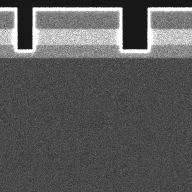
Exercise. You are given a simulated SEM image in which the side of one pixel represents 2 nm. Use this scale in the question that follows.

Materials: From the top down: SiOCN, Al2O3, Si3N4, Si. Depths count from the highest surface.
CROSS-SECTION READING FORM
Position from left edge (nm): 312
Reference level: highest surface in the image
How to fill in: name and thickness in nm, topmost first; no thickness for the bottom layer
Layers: SiOCN 42, Al2O3 32, Si3N4 26, Si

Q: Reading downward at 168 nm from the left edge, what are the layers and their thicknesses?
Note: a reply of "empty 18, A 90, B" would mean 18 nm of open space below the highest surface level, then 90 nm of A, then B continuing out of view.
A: SiOCN 42, Al2O3 32, Si3N4 26, Si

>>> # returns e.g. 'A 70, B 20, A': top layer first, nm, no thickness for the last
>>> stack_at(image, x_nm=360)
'SiOCN 42, Al2O3 32, Si3N4 26, Si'